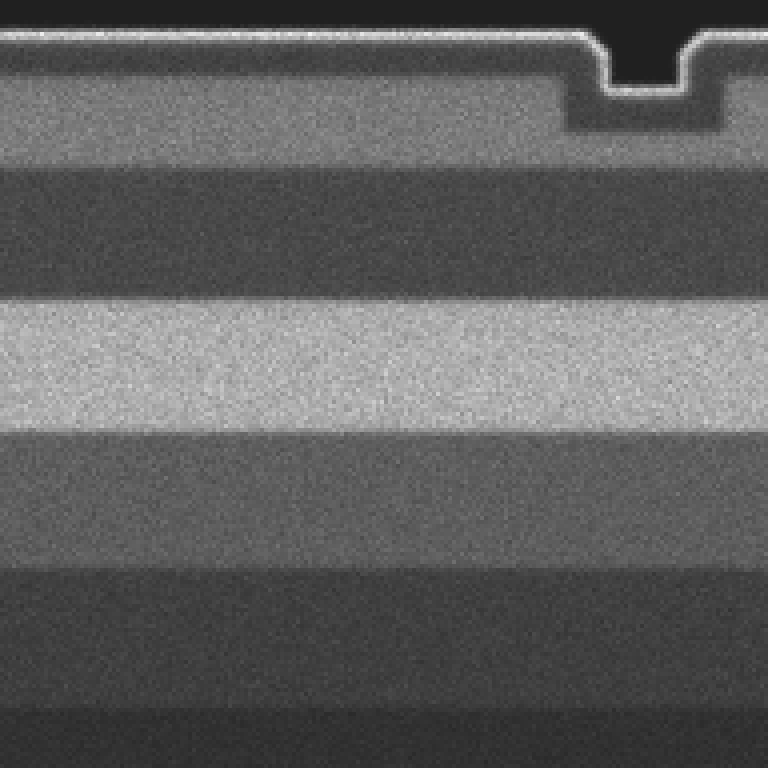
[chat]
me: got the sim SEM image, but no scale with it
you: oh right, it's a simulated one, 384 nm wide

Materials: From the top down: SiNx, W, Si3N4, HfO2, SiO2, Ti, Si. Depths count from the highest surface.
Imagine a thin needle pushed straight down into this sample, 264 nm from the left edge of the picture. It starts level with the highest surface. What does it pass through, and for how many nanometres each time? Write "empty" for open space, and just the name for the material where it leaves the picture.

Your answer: SiNx 22, W 46, Si3N4 66, HfO2 66, SiO2 68, Ti 70, Si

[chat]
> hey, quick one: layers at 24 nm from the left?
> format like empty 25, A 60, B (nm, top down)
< SiNx 22, W 46, Si3N4 66, HfO2 66, SiO2 68, Ti 70, Si